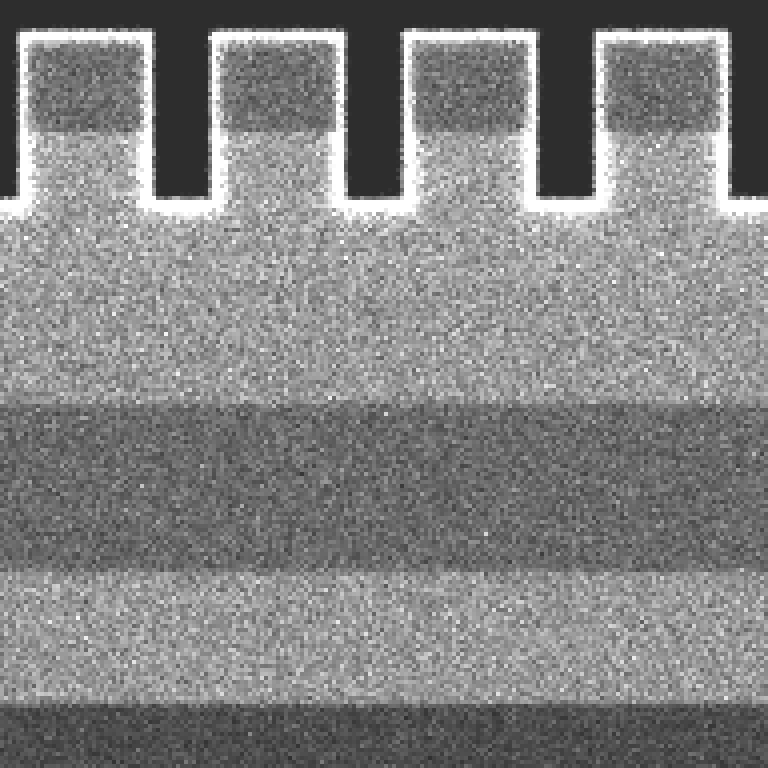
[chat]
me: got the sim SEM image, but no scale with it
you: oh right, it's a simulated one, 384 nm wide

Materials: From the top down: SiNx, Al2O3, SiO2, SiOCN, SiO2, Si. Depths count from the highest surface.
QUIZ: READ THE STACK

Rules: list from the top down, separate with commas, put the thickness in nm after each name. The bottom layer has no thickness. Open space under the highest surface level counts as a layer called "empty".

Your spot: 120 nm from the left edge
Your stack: SiNx 50, Al2O3 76, SiO2 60, SiOCN 84, SiO2 66, Si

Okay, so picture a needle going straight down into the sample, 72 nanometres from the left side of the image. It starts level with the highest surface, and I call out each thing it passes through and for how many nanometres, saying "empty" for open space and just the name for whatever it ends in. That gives SiNx 50, Al2O3 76, SiO2 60, SiOCN 84, SiO2 66, Si